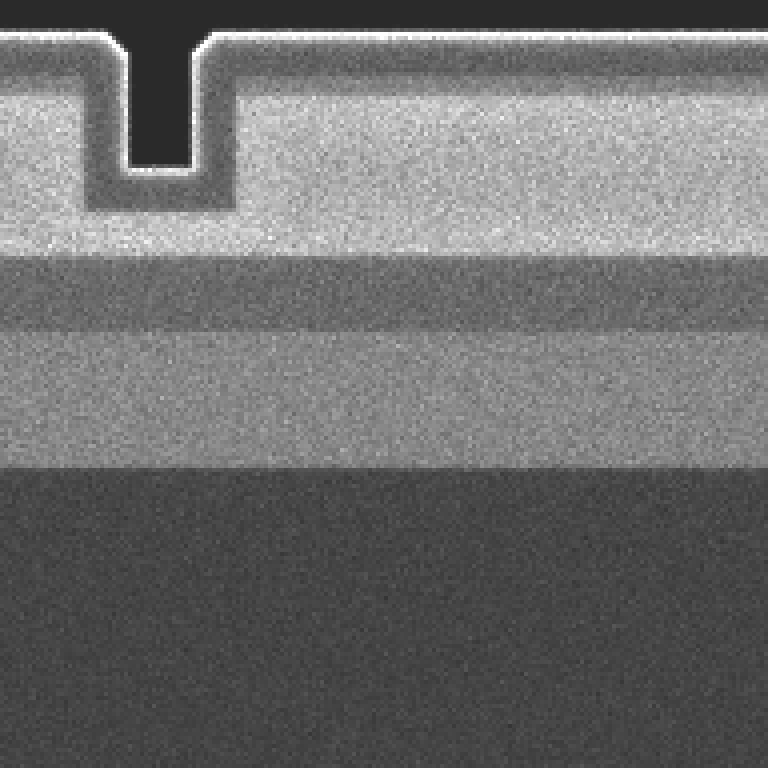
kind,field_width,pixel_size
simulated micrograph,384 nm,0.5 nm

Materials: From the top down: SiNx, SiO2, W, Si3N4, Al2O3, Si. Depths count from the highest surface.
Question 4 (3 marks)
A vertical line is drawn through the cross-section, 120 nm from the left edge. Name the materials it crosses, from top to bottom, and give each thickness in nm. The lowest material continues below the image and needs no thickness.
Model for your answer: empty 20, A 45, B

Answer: SiNx 22, SiO2 10, W 80, Si3N4 38, Al2O3 68, Si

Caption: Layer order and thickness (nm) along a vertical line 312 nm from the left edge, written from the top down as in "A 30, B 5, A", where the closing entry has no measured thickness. SiNx 22, SiO2 10, W 80, Si3N4 38, Al2O3 68, Si